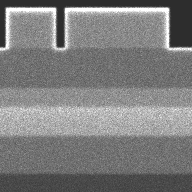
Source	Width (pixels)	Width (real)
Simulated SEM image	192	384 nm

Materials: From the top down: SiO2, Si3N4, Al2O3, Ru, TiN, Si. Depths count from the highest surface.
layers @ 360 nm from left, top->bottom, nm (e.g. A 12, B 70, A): empty 80, Si3N4 80, Al2O3 38, Ru 58, TiN 76, Si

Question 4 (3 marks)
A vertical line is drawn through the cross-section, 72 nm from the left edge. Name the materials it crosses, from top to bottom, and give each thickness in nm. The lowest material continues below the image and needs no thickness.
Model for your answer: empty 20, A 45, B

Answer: SiO2 80, Si3N4 80, Al2O3 38, Ru 58, TiN 76, Si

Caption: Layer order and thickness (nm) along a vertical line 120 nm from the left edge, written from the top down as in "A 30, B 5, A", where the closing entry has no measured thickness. empty 80, Si3N4 80, Al2O3 38, Ru 58, TiN 76, Si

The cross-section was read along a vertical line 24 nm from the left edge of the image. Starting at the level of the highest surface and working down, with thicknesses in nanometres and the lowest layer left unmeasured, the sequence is SiO2 80, Si3N4 80, Al2O3 38, Ru 58, TiN 76, Si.